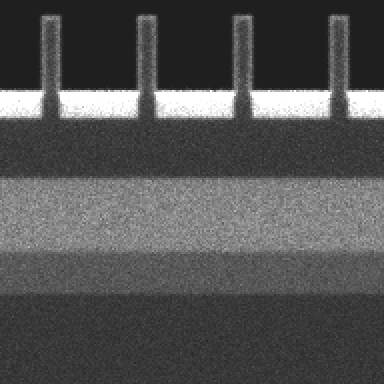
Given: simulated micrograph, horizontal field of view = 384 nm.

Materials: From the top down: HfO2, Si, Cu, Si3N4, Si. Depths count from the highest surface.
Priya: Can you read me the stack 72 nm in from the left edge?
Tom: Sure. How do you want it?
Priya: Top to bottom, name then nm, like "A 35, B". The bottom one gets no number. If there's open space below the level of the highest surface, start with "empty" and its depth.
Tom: empty 76, HfO2 26, Si 60, Cu 74, Si3N4 42, Si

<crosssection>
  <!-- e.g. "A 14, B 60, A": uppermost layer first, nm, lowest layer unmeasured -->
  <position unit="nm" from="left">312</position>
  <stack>empty 76, HfO2 26, Si 60, Cu 74, Si3N4 42, Si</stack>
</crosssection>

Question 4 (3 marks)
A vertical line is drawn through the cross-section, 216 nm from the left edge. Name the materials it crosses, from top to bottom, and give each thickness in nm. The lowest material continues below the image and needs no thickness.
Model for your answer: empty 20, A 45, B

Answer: empty 76, HfO2 26, Si 60, Cu 74, Si3N4 42, Si